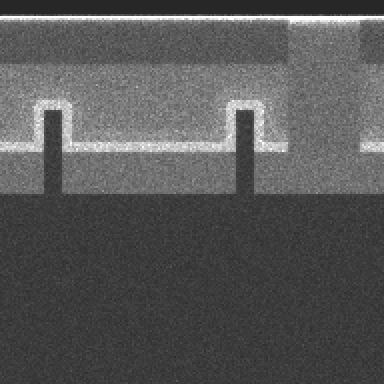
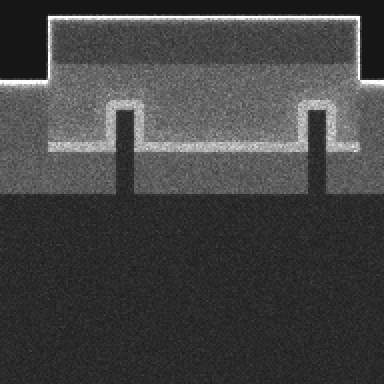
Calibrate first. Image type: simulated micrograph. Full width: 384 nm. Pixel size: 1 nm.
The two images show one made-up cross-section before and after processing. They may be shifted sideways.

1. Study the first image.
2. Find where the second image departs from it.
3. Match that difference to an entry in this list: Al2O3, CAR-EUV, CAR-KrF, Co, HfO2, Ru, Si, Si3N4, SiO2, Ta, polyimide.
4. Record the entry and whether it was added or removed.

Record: SiO2 / removed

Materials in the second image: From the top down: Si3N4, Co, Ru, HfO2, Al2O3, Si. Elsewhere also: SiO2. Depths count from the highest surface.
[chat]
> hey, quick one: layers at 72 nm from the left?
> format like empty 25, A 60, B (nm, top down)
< Si3N4 48, Co 66, Ru 12, HfO2 10, Al2O3 42, Si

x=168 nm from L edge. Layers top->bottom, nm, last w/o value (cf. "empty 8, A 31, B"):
Si3N4 48, Co 66, Ru 12, HfO2 10, Al2O3 42, Si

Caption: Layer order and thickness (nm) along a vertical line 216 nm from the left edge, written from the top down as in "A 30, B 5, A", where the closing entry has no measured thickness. Si3N4 48, Co 66, Ru 12, HfO2 10, Al2O3 42, Si